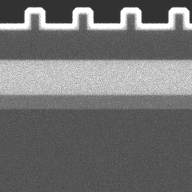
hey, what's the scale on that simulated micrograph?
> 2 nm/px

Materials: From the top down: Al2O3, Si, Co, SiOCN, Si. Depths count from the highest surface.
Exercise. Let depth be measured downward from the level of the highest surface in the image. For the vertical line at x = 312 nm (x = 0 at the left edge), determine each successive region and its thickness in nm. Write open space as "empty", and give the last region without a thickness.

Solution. empty 32, Al2O3 12, Si 60, Co 70, SiOCN 28, Si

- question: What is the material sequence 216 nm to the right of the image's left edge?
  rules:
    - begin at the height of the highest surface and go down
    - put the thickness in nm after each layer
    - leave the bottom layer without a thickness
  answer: empty 32, Al2O3 12, Si 60, Co 70, SiOCN 28, Si